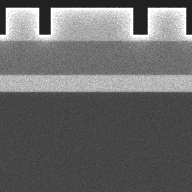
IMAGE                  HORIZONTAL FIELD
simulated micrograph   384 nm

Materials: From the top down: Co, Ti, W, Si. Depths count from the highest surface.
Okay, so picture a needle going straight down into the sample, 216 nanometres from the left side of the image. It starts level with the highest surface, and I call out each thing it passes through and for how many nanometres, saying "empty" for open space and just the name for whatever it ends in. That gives Co 66, Ti 68, W 34, Si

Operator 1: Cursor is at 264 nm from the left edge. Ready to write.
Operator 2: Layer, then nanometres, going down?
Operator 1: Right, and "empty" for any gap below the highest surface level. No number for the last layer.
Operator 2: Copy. Co 66, Ti 68, W 34, Si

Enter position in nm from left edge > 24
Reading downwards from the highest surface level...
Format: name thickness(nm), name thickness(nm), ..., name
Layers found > Co 66, Ti 68, W 34, Si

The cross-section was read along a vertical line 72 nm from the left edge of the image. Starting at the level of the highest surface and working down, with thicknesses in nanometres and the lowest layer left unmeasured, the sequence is Co 66, Ti 68, W 34, Si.